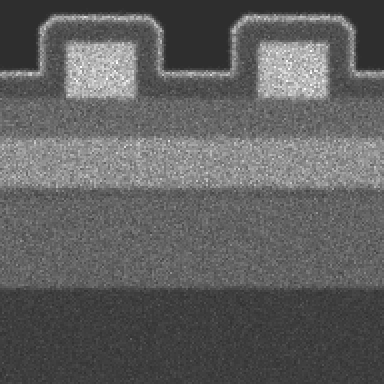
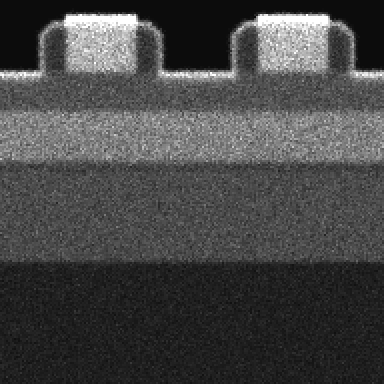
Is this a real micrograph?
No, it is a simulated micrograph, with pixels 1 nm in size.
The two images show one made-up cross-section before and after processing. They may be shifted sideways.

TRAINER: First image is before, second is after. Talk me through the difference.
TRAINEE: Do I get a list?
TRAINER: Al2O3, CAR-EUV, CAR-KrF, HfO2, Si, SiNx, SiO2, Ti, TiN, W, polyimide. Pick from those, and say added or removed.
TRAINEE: removed: SiNx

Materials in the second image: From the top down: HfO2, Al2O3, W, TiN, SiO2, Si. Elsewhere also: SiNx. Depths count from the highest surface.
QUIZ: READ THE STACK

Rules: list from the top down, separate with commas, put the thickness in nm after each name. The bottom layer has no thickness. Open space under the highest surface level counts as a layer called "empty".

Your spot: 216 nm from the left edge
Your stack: empty 56, Al2O3 40, W 50, TiN 10, SiO2 90, Si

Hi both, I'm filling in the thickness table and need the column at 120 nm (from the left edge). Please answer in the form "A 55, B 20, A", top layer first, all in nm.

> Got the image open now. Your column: HfO2 56, Al2O3 40, W 50, TiN 10, SiO2 90, Si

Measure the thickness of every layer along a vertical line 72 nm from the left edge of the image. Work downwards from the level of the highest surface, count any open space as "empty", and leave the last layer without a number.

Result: HfO2 56, Al2O3 40, W 50, TiN 10, SiO2 90, Si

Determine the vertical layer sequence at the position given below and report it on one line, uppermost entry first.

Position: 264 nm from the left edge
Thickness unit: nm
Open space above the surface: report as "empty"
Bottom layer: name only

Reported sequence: HfO2 56, Al2O3 40, W 50, TiN 10, SiO2 90, Si